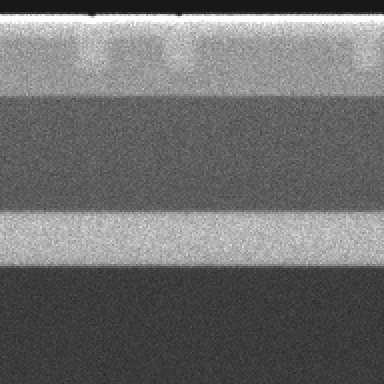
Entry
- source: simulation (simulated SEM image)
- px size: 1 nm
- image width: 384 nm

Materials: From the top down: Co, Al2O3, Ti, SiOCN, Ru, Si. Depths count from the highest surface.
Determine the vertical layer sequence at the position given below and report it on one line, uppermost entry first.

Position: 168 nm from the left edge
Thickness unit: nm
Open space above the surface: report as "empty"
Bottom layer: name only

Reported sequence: Co 54, Al2O3 26, Ti 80, SiOCN 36, Ru 54, Si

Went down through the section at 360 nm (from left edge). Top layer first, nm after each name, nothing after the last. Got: Co 54, Al2O3 26, Ti 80, SiOCN 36, Ru 54, Si